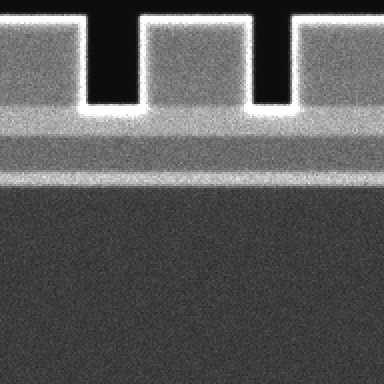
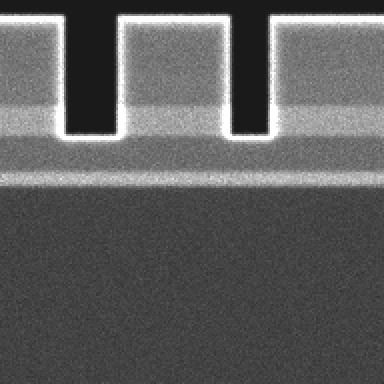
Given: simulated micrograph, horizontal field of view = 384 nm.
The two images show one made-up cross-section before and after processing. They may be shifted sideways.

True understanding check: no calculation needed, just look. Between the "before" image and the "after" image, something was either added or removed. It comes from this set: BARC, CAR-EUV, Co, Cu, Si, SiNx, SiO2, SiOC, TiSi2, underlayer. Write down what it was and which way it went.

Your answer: SiO2 (removed)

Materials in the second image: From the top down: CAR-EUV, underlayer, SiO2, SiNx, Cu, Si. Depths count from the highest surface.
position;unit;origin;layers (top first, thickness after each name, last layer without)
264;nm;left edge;empty 120, SiNx 36, Cu 14, Si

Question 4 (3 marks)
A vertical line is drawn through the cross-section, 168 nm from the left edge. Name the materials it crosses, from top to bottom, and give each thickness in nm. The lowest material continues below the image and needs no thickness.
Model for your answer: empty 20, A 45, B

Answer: CAR-EUV 56, underlayer 34, SiO2 30, SiNx 36, Cu 14, Si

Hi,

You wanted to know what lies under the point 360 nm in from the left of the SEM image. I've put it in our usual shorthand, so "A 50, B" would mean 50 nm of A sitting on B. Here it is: CAR-EUV 56, underlayer 34, SiO2 30, SiNx 36, Cu 14, Si